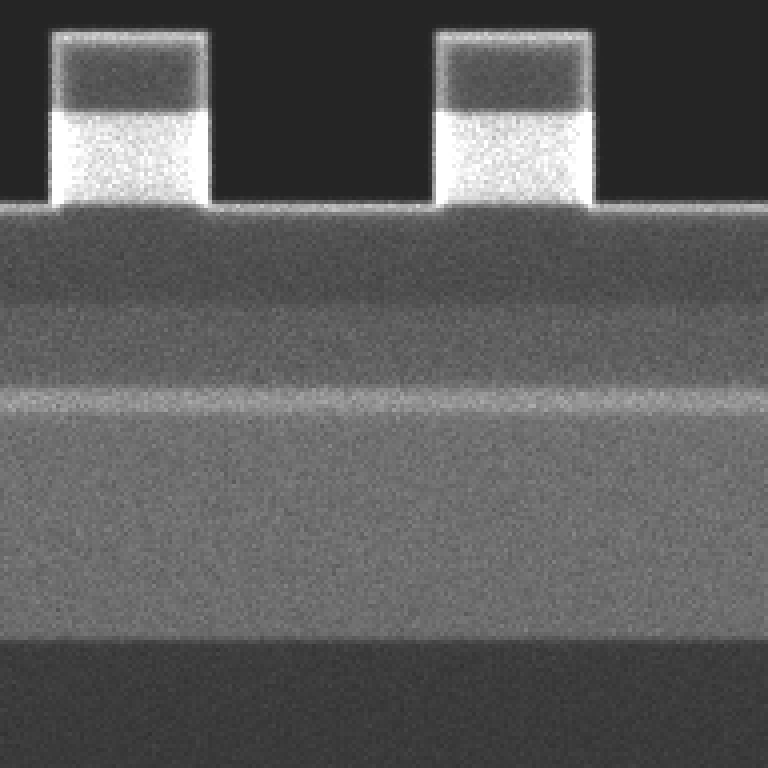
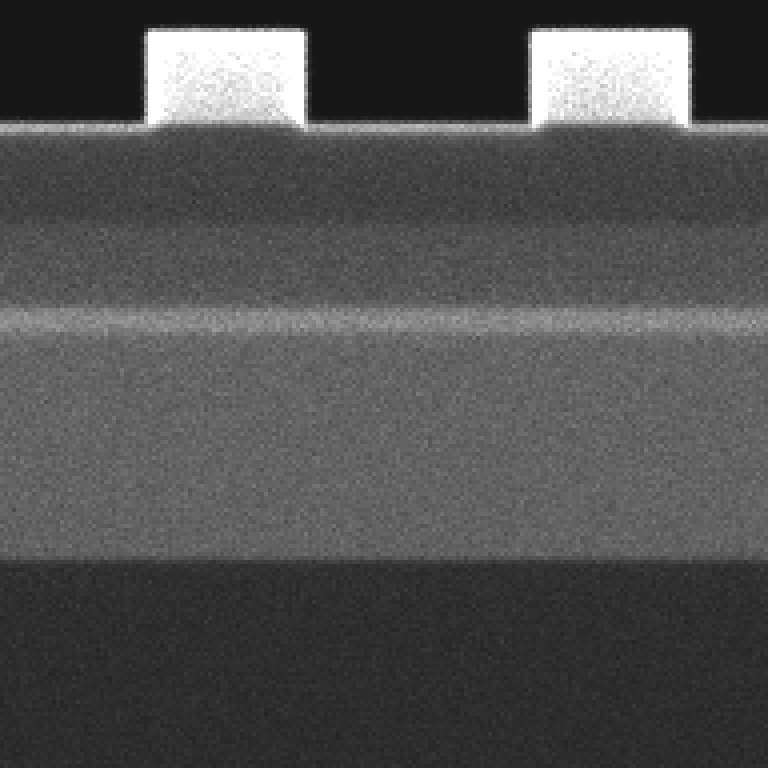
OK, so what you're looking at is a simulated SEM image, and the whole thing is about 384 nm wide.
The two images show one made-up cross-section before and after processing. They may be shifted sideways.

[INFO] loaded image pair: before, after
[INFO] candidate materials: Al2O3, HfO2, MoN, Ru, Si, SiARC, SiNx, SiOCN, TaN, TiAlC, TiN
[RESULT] removed SiARC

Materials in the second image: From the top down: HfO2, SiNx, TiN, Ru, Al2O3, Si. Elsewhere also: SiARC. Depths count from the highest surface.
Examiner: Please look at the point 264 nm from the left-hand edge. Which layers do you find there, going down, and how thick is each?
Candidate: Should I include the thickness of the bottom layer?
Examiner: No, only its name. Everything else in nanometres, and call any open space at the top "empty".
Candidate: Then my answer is empty 46, SiNx 50, TiN 42, Ru 12, Al2O3 114, Si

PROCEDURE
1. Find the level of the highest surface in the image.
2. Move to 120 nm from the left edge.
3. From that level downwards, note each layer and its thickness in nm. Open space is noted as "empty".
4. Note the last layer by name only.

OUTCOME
HfO2 46, SiNx 50, TiN 42, Ru 12, Al2O3 114, Si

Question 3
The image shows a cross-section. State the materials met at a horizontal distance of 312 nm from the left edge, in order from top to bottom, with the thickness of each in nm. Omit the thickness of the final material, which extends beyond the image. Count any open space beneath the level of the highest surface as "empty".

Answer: HfO2 46, SiNx 50, TiN 42, Ru 12, Al2O3 114, Si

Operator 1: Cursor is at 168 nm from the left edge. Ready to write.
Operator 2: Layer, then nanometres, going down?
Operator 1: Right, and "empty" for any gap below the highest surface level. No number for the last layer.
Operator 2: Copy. empty 46, SiNx 50, TiN 42, Ru 12, Al2O3 114, Si